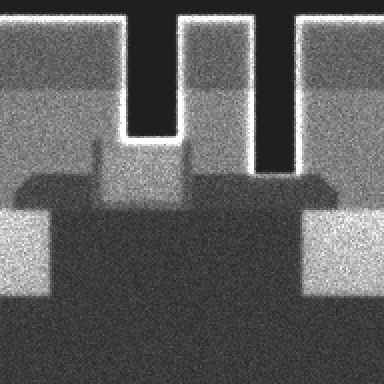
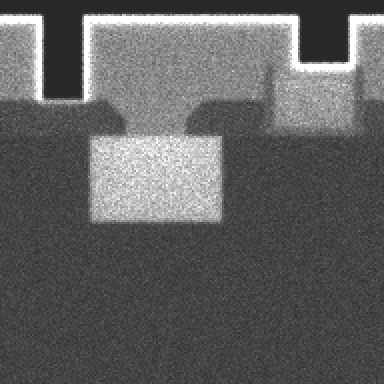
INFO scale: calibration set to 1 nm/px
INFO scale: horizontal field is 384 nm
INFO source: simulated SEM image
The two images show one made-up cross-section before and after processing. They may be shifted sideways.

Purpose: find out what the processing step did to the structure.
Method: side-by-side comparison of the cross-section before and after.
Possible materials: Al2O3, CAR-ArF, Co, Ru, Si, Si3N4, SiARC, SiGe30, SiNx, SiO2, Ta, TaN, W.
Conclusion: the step removed SiARC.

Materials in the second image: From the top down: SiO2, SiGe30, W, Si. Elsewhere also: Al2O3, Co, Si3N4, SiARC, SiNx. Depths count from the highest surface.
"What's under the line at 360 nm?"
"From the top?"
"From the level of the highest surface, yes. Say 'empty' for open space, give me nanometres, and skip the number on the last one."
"SiO2 50, SiNx 70, Si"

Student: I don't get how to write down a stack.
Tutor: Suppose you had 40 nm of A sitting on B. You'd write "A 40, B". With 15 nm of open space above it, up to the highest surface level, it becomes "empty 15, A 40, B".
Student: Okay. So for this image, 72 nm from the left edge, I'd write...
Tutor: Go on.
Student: empty 84, SiGe30 36, Si